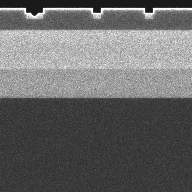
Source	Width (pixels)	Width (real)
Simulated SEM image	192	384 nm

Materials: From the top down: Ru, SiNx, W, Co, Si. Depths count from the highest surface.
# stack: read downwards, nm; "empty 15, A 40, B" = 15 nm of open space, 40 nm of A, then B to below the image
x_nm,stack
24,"SiNx 44, W 78, Co 58, Si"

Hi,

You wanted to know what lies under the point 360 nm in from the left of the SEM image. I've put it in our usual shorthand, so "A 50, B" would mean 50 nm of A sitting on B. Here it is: SiNx 44, W 78, Co 58, Si